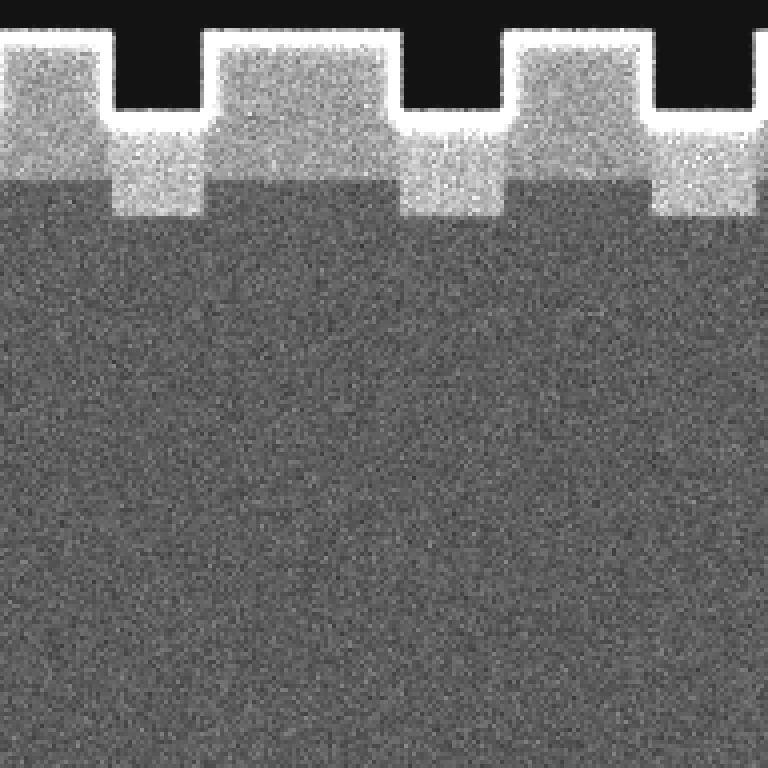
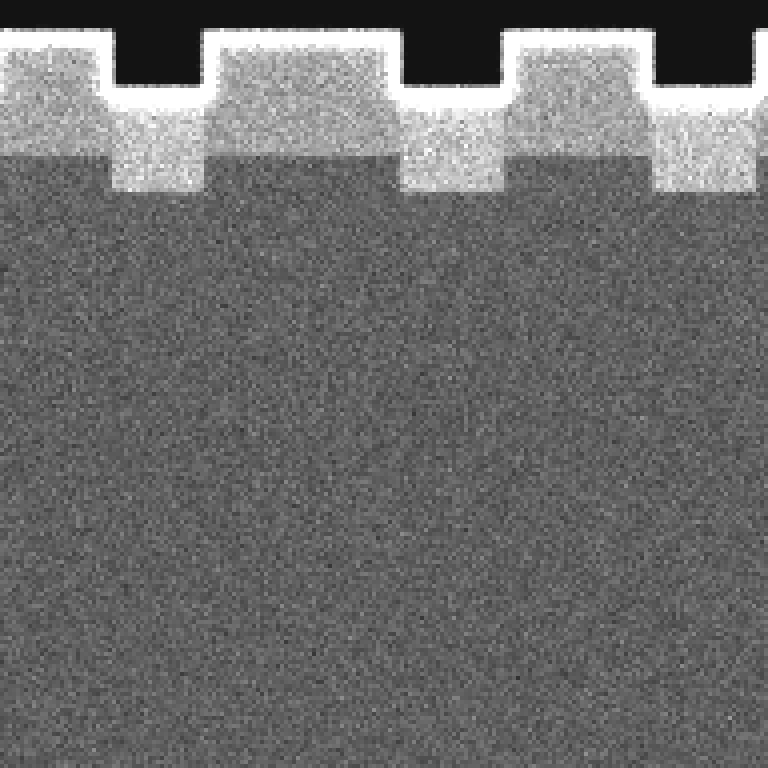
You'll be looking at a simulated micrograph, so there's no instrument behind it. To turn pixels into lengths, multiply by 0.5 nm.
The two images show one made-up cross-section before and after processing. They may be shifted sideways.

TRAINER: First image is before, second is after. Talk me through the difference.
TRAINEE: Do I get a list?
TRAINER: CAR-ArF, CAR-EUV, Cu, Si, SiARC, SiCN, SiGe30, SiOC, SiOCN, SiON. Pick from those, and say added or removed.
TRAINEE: removed: SiOCN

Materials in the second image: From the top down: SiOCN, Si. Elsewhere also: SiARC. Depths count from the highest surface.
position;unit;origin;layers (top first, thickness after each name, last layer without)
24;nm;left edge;SiOCN 62, Si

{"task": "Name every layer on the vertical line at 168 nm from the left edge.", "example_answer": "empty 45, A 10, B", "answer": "SiOCN 62, Si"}